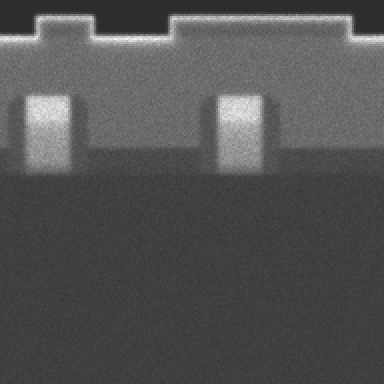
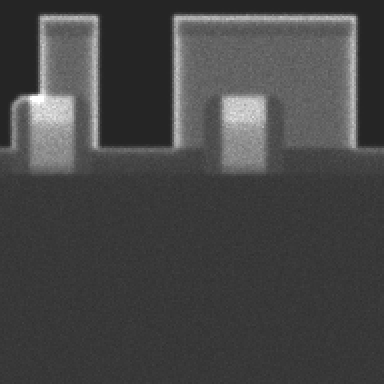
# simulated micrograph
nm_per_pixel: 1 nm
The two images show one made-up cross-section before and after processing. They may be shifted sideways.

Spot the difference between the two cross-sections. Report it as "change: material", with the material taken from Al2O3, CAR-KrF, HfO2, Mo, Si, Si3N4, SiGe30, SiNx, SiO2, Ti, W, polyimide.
removed: SiO2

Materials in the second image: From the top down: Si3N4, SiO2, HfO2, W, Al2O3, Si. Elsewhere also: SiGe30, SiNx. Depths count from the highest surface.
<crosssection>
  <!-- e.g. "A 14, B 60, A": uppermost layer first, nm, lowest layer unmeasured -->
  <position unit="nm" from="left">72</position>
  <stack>Si3N4 20, SiO2 60, HfO2 26, W 44, Al2O3 8, Si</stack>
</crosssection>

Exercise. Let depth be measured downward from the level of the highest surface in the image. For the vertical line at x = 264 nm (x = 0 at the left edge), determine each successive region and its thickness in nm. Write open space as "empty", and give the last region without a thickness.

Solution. Si3N4 20, SiO2 60, HfO2 26, W 44, Al2O3 8, Si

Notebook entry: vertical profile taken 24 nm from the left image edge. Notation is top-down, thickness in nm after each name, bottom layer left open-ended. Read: empty 80, SiNx 78, Si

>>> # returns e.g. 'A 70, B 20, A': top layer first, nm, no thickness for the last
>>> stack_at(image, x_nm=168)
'empty 132, SiGe30 26, Si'